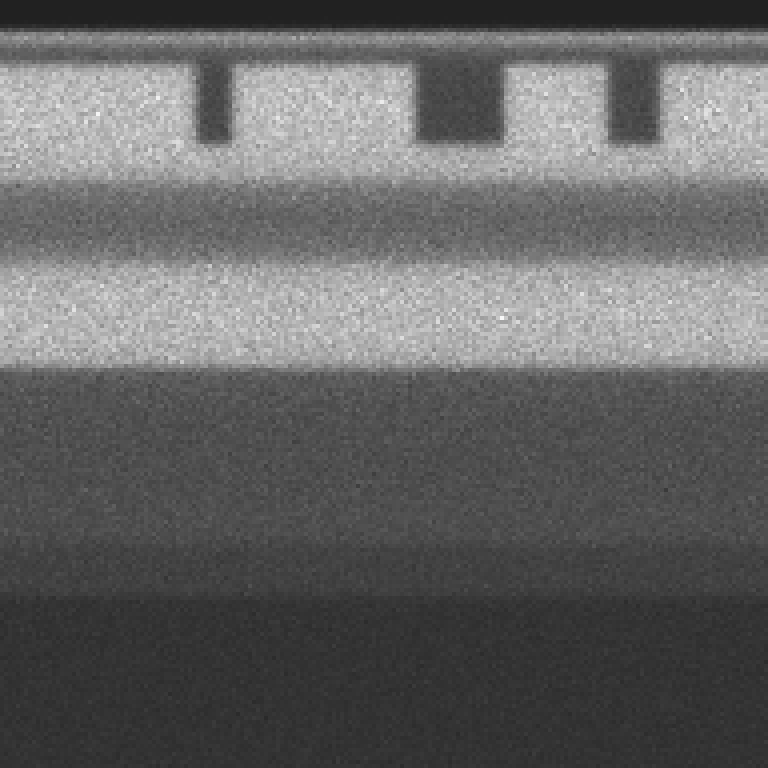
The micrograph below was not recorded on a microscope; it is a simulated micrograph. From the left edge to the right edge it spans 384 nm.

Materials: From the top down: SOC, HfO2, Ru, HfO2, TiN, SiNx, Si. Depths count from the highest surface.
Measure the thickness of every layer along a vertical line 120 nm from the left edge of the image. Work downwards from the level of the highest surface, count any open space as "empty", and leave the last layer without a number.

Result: SOC 16, HfO2 58, Ru 42, HfO2 52, TiN 88, SiNx 26, Si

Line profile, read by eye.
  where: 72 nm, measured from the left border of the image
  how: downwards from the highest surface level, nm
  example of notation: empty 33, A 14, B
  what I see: SOC 16, HfO2 58, Ru 42, HfO2 52, TiN 88, SiNx 26, Si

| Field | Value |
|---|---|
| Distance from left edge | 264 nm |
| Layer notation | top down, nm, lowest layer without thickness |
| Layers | SOC 16, HfO2 58, Ru 42, HfO2 52, TiN 88, SiNx 26, Si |